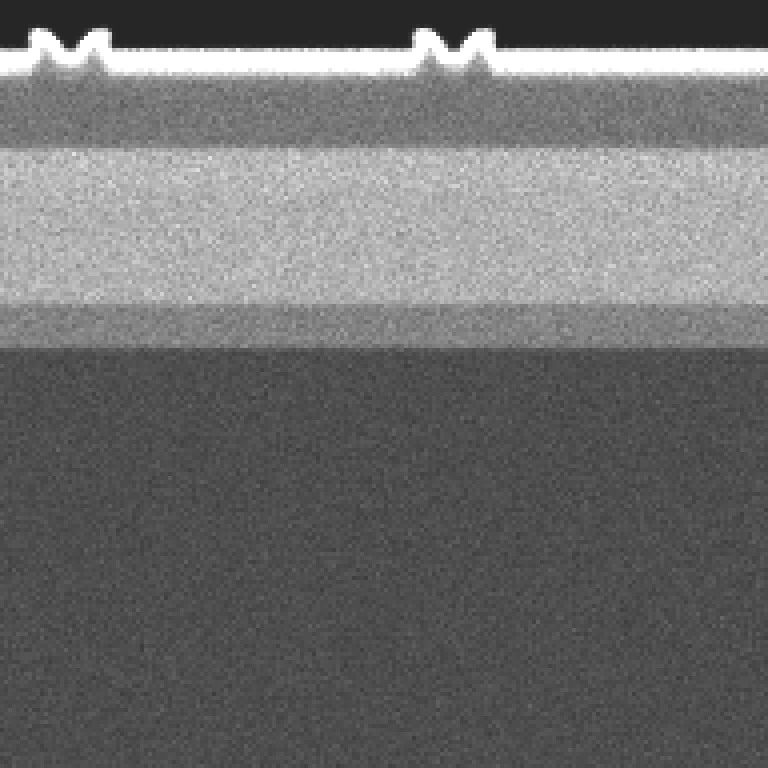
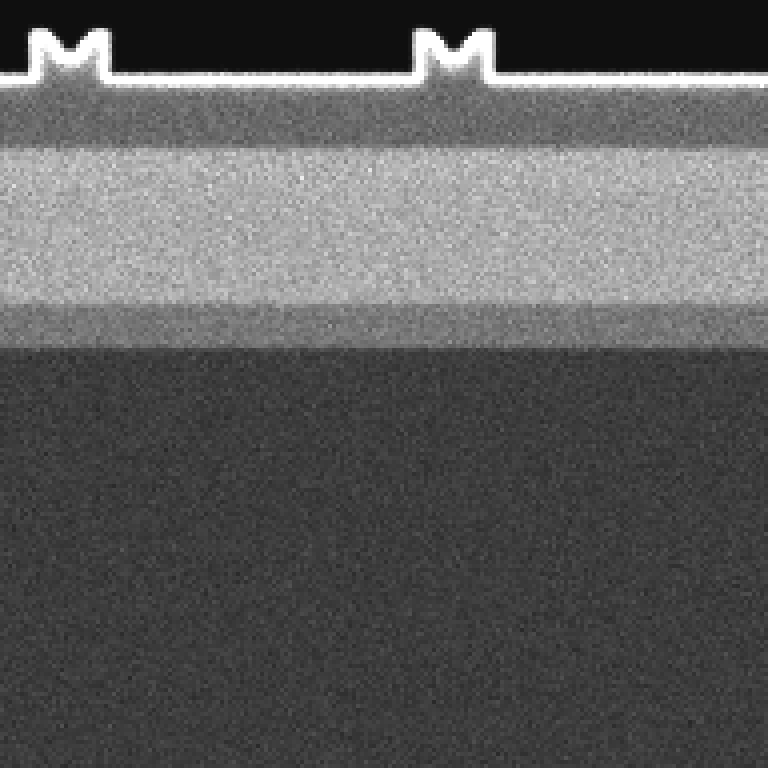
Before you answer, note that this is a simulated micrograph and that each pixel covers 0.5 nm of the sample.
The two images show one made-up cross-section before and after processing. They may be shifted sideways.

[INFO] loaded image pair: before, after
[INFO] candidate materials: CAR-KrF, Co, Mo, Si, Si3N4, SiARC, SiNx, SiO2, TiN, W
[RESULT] removed SiO2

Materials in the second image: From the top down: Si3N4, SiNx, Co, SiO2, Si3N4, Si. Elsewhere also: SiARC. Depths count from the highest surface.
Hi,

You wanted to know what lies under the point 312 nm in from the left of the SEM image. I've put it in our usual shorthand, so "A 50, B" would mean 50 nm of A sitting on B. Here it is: empty 22, SiNx 36, Co 18, SiO2 60, Si3N4 22, Si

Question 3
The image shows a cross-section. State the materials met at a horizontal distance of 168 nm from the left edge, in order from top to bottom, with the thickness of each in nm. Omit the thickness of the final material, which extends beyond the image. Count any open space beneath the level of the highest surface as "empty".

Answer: empty 22, SiNx 36, Co 18, SiO2 60, Si3N4 22, Si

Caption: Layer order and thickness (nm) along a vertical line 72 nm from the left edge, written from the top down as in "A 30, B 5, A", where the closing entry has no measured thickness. empty 22, SiNx 36, Co 18, SiO2 60, Si3N4 22, Si